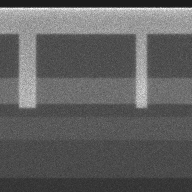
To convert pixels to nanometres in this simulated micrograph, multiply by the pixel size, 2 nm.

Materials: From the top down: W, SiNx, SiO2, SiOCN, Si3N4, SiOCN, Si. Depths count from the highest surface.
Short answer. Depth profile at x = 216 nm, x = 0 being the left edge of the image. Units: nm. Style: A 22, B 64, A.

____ W 52, SiNx 88, SiO2 52, SiOCN 26, Si3N4 46, SiOCN 76, Si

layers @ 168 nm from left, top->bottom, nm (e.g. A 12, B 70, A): W 52, SiNx 88, SiO2 52, SiOCN 26, Si3N4 46, SiOCN 76, Si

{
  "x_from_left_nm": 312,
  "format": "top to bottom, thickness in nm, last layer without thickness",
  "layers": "W 52, SiNx 88, SiO2 52, SiOCN 26, Si3N4 46, SiOCN 76, Si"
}